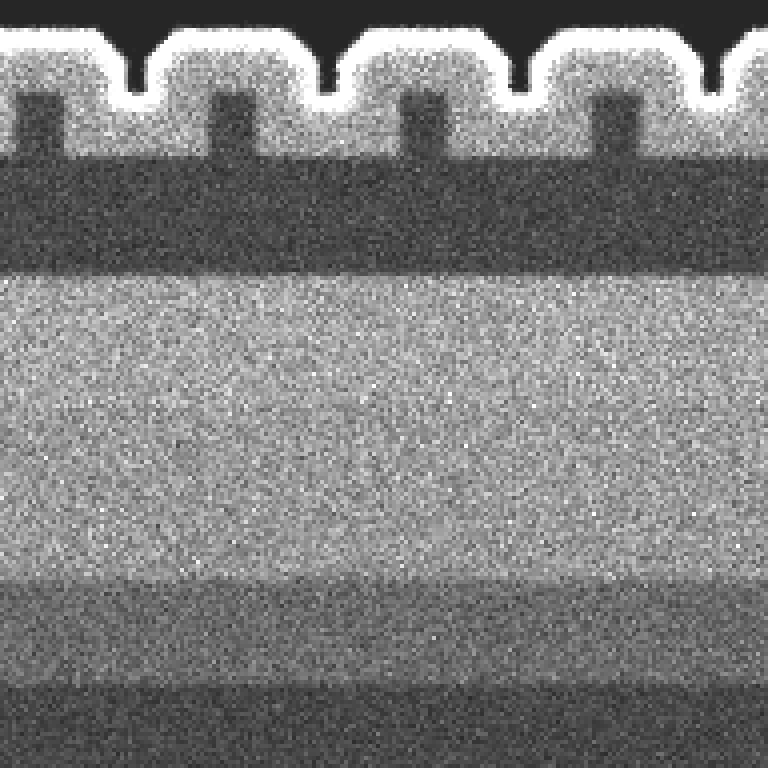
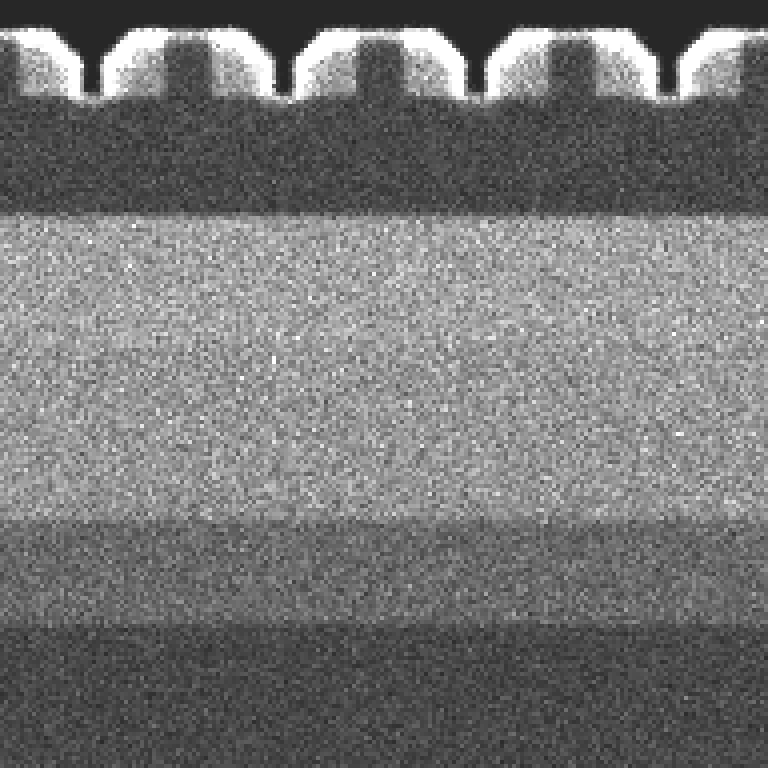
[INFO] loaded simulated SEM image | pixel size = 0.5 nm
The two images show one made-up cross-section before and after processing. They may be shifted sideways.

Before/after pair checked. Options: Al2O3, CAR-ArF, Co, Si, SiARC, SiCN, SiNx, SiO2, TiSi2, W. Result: removed SiO2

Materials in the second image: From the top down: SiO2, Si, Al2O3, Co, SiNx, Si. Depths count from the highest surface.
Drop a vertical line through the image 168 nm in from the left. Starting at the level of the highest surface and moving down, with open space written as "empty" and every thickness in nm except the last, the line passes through SiO2 32, Si 60, Al2O3 64, Co 88, SiNx 52, Si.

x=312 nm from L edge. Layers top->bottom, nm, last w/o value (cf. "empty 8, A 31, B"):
SiO2 32, Si 60, Al2O3 64, Co 88, SiNx 52, Si